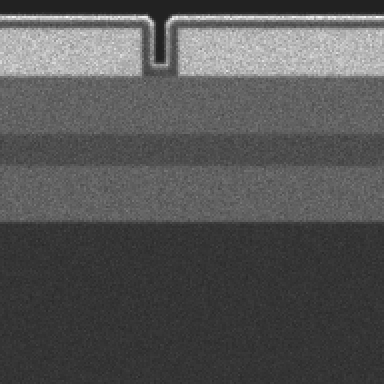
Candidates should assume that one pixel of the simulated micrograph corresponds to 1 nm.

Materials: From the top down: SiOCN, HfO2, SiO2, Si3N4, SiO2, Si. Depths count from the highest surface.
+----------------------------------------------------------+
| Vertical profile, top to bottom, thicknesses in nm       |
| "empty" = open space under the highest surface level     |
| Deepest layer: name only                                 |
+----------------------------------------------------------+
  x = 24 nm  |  SiOCN 12, HfO2 48, SiO2 58, Si3N4 32, SiO2 56, Si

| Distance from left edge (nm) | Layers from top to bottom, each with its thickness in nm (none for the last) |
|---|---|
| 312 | SiOCN 12, HfO2 48, SiO2 58, Si3N4 32, SiO2 56, Si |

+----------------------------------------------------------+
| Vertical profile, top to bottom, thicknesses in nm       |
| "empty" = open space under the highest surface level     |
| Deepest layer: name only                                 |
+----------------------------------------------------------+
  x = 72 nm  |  SiOCN 12, HfO2 48, SiO2 58, Si3N4 32, SiO2 56, Si